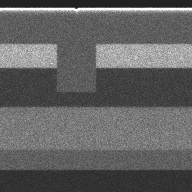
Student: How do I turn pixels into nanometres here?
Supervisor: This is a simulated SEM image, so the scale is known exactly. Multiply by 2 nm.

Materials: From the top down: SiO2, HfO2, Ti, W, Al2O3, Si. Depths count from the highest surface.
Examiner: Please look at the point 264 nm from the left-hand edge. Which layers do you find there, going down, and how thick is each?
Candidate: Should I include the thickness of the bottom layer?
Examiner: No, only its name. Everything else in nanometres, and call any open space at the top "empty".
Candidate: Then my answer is SiO2 72, HfO2 48, Ti 78, W 86, Al2O3 40, Si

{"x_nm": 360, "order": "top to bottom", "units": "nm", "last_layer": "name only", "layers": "SiO2 72, HfO2 48, Ti 78, W 86, Al2O3 40, Si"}